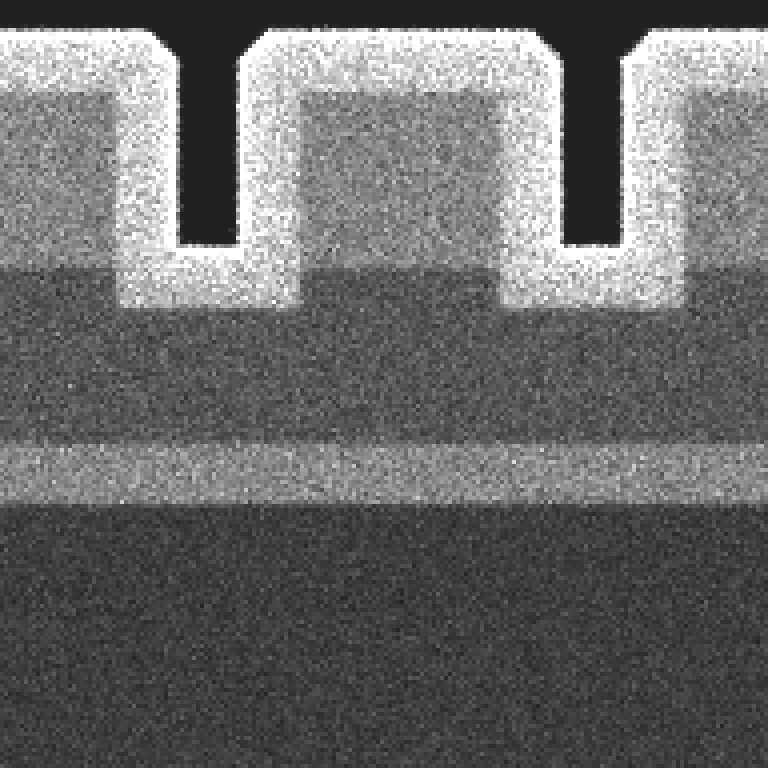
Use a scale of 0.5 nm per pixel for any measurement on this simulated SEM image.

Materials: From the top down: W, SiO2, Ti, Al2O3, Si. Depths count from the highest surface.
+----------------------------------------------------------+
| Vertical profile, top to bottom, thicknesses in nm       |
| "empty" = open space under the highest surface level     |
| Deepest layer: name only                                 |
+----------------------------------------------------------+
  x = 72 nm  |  W 138, Ti 68, Al2O3 30, Si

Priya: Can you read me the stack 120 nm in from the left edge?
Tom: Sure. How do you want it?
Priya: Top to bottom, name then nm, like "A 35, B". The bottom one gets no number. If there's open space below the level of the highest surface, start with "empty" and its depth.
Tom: empty 14, W 124, Ti 68, Al2O3 30, Si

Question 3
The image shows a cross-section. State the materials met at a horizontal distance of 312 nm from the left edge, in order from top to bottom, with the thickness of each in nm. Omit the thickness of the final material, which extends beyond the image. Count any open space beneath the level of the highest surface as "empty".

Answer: empty 14, W 124, Ti 68, Al2O3 30, Si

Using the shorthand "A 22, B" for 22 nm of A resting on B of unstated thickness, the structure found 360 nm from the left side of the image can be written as W 30, SiO2 88, Ti 88, Al2O3 30, Si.